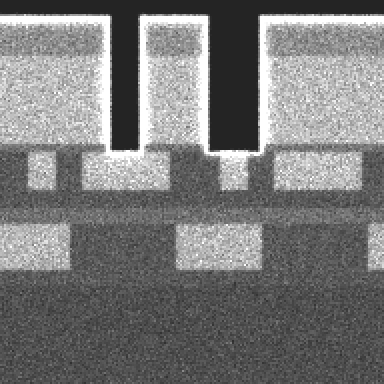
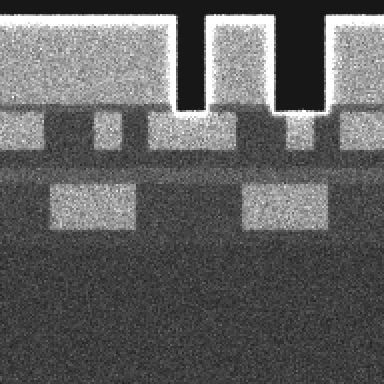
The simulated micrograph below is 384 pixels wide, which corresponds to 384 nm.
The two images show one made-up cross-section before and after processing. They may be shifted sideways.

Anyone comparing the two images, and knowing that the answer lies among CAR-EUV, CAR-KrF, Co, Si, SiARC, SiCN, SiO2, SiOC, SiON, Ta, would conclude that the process removed SiARC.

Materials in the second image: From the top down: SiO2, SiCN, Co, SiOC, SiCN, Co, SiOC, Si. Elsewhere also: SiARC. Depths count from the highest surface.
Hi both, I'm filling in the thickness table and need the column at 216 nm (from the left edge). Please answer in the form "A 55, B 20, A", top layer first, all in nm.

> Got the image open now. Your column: SiO2 88, SiCN 8, Co 38, SiOC 18, SiCN 16, SiOC 62, Si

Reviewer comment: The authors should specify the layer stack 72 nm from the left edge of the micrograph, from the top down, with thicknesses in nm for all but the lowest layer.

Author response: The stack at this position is SiO2 88, SiCN 8, SiOC 56, SiCN 16, Co 46, SiOC 16, Si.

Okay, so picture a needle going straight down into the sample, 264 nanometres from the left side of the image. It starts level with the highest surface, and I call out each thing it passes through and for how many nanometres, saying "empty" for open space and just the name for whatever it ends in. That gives SiO2 88, SiCN 8, SiOC 56, SiCN 16, Co 46, SiOC 16, Si